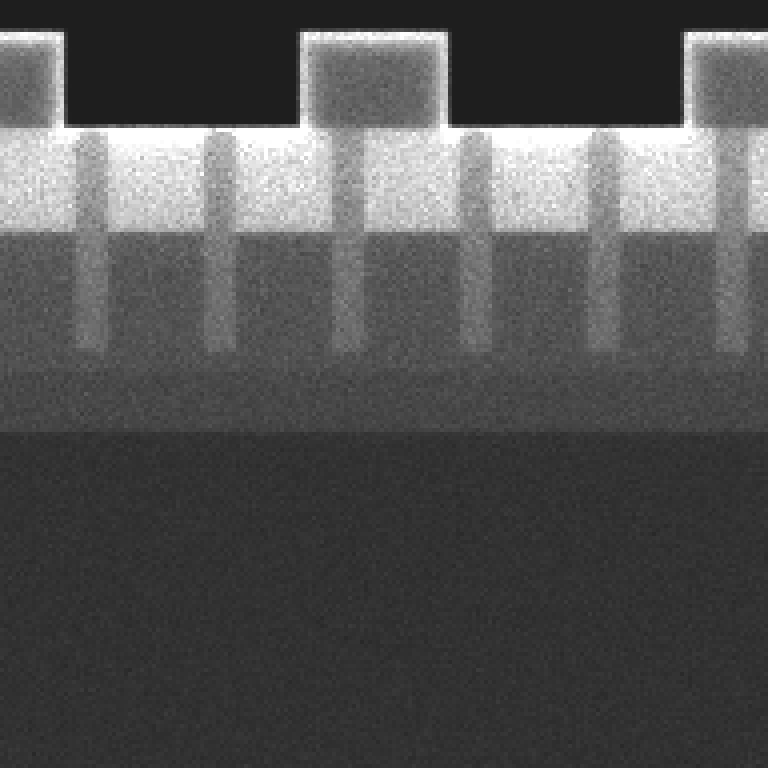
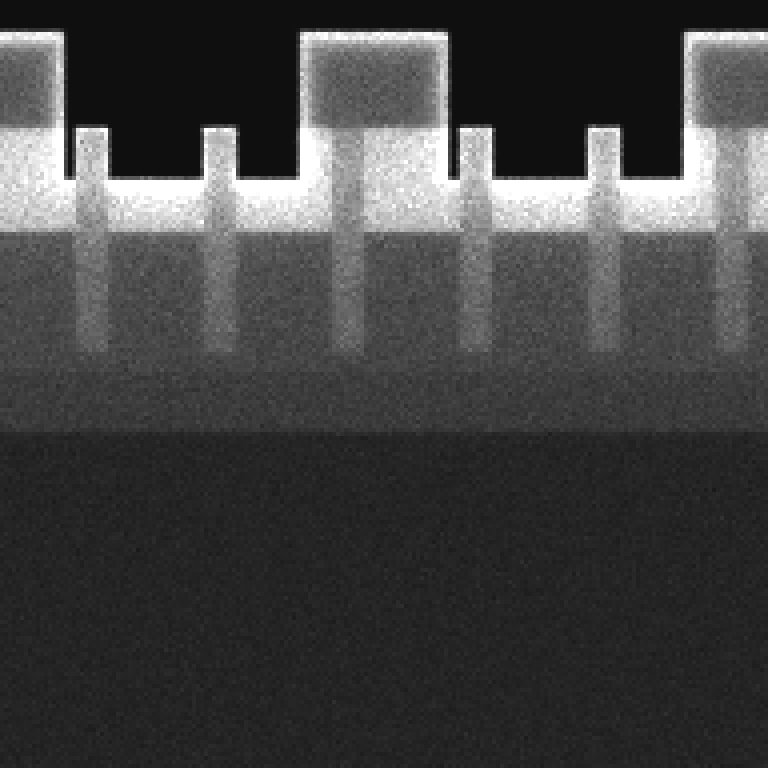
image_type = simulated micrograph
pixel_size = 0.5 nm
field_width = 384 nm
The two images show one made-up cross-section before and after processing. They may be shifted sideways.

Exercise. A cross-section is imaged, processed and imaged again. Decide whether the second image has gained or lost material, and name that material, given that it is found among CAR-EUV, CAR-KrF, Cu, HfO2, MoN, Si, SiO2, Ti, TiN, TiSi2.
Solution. removed: HfO2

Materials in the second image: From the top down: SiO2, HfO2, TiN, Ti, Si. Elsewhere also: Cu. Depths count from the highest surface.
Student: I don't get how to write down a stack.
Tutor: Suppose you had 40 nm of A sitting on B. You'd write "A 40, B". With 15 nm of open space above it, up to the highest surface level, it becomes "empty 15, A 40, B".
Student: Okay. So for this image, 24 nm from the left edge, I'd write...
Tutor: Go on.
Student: SiO2 48, HfO2 52, TiN 70, Ti 30, Si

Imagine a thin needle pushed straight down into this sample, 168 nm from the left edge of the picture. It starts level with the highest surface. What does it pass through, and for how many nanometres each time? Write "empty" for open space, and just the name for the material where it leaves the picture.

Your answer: SiO2 48, Cu 112, TiN 10, Ti 30, Si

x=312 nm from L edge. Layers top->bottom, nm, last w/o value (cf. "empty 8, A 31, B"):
empty 74, HfO2 26, TiN 70, Ti 30, Si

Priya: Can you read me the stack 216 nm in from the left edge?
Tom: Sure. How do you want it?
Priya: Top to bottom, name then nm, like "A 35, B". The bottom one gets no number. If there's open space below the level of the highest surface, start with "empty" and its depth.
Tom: SiO2 48, HfO2 52, TiN 70, Ti 30, Si